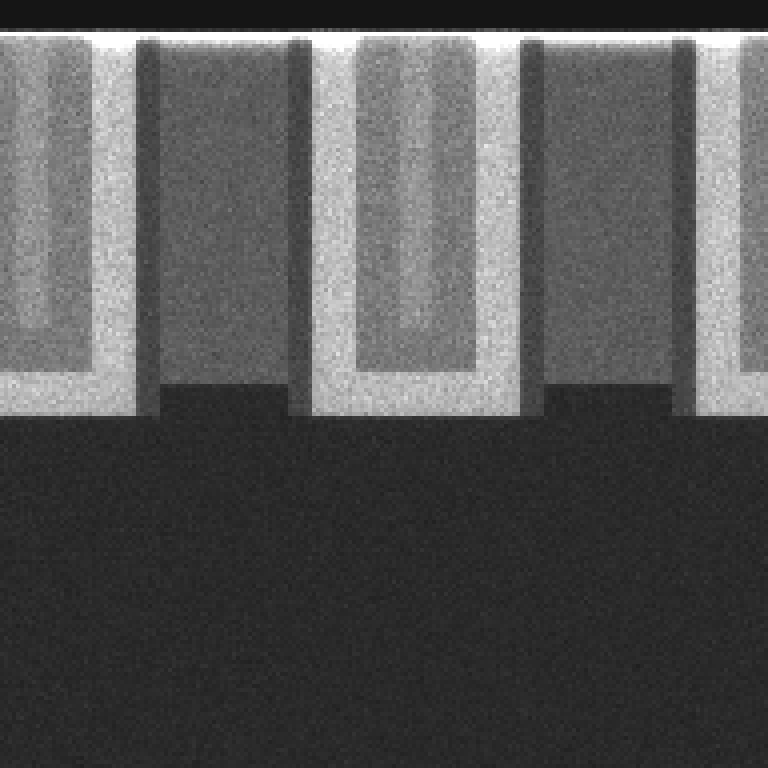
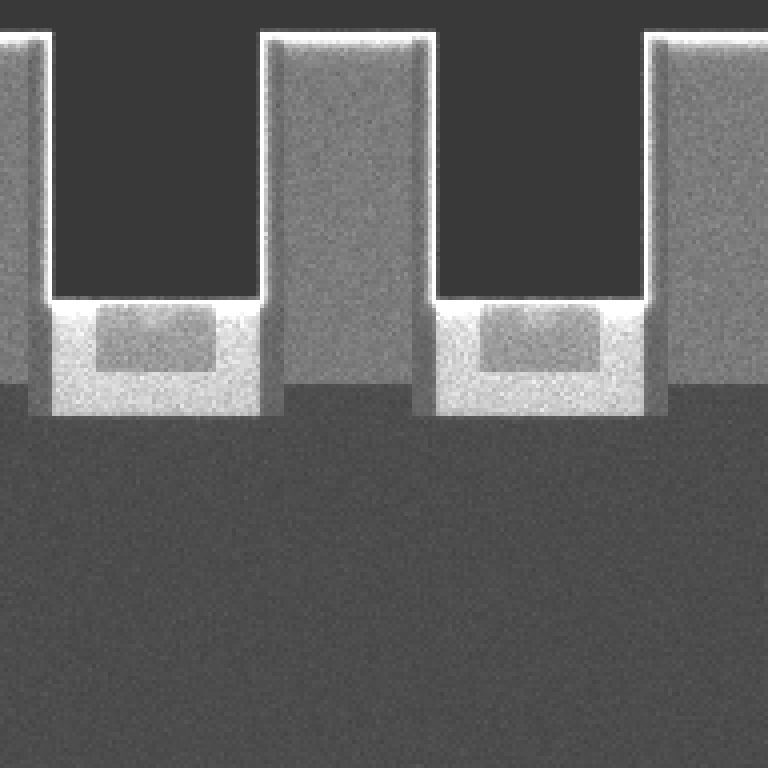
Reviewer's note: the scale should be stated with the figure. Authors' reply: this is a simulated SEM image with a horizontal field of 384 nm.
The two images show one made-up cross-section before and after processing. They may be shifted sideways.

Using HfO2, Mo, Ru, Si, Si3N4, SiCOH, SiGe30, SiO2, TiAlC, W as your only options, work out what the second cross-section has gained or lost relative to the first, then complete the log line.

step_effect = removed HfO2 and Ru and W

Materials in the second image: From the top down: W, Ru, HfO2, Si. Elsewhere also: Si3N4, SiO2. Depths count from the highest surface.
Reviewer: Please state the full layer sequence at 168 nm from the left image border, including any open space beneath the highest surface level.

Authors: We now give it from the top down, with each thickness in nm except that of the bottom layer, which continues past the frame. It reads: SiO2 176, Si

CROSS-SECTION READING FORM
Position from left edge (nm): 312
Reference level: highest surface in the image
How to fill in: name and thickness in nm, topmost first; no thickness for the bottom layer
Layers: empty 134, HfO2 58, Si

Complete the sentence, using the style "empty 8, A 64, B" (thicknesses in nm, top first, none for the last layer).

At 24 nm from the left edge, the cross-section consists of Si3N4 192, Si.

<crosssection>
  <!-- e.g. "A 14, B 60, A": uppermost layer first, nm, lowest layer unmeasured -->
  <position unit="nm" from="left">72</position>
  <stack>empty 134, W 14, Ru 22, HfO2 22, Si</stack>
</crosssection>